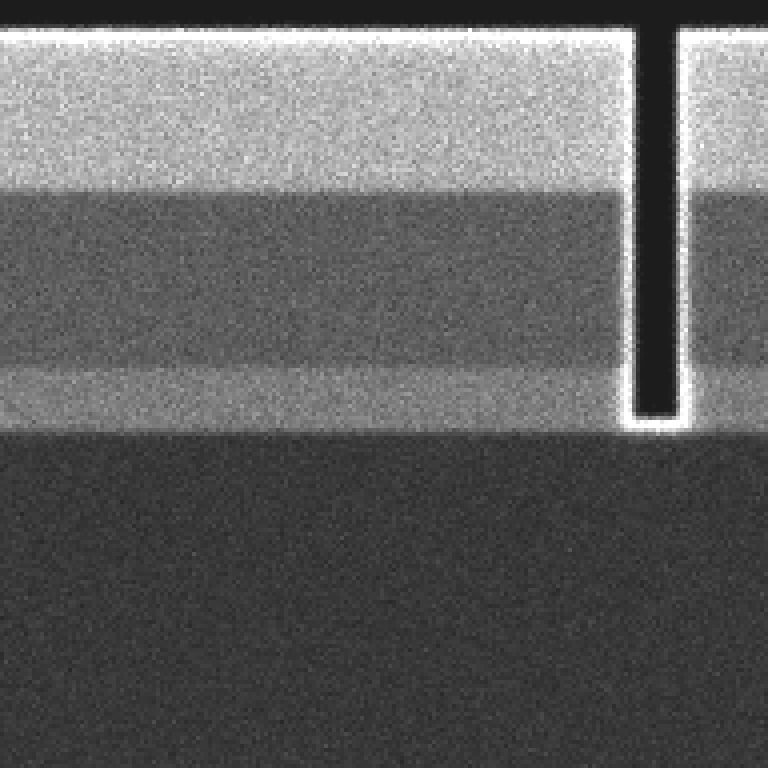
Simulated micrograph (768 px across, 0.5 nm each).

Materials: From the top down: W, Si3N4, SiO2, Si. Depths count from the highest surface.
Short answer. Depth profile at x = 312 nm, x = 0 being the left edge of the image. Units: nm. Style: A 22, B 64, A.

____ W 80, Si3N4 88, SiO2 32, Si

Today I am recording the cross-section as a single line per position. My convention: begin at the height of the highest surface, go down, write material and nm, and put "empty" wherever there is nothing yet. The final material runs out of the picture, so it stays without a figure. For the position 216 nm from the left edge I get W 80, Si3N4 88, SiO2 32, Si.